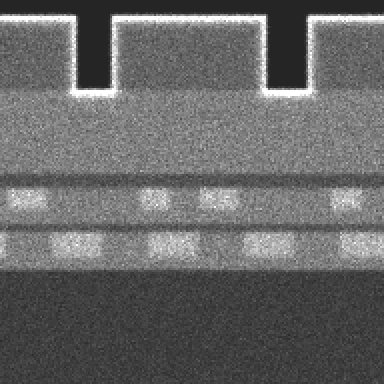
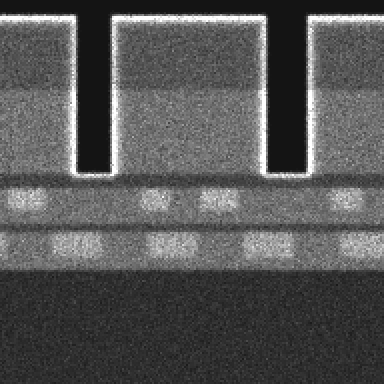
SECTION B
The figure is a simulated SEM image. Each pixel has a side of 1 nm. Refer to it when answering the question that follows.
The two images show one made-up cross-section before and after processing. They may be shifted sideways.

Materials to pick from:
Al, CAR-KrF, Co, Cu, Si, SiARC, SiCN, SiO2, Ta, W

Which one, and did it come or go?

SiO2 - removed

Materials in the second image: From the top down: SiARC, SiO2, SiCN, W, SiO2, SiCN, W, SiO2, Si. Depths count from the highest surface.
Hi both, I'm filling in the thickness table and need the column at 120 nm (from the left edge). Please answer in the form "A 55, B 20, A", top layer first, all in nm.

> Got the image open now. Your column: SiARC 74, SiO2 84, SiCN 14, SiO2 36, SiCN 8, SiO2 38, Si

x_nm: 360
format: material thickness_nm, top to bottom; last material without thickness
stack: SiARC 74, SiO2 84, SiCN 14, W 22, SiO2 14, SiCN 8, W 26, SiO2 12, Si